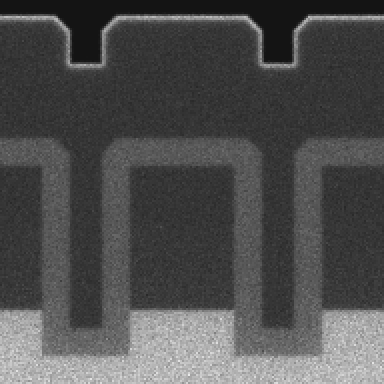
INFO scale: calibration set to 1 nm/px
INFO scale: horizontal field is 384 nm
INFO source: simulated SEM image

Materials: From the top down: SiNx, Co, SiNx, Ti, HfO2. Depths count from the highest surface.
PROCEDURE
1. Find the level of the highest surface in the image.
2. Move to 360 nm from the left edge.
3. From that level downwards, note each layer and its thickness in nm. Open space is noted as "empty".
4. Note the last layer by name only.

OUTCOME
SiNx 122, Co 28, SiNx 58, Ti 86, HfO2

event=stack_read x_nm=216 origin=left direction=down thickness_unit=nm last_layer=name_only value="SiNx 122, Co 28, SiNx 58, Ti 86, HfO2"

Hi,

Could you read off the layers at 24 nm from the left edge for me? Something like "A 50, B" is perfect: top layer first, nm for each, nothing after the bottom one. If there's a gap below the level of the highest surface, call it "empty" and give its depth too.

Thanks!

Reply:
SiNx 122, Co 28, SiNx 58, Ti 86, HfO2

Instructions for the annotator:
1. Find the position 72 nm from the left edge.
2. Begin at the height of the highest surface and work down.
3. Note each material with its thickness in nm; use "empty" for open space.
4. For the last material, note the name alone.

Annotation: empty 48, SiNx 264, Co 28, HfO2